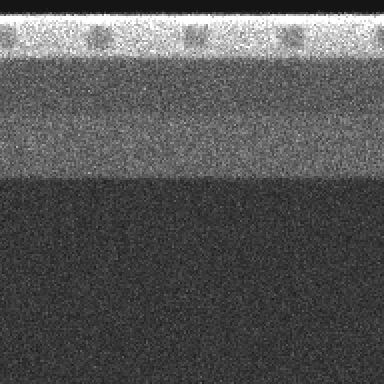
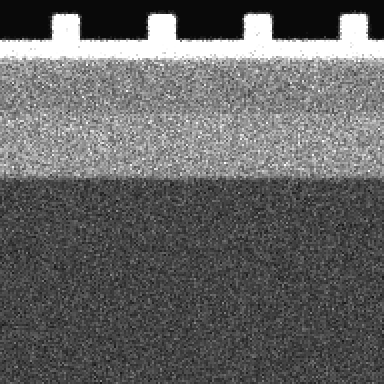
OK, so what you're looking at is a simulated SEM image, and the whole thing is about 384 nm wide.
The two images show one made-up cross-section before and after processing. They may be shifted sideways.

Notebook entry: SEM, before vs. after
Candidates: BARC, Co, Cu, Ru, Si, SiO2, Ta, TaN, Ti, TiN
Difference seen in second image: Ru removed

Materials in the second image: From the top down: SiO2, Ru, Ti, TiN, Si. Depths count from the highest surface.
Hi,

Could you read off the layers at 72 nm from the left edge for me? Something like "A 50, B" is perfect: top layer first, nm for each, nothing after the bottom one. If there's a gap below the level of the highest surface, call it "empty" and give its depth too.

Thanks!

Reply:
SiO2 32, Ru 10, Ti 56, TiN 64, Si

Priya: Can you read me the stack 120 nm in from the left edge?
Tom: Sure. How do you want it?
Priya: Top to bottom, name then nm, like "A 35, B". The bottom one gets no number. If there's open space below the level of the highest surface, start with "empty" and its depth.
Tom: empty 26, Ru 16, Ti 56, TiN 64, Si